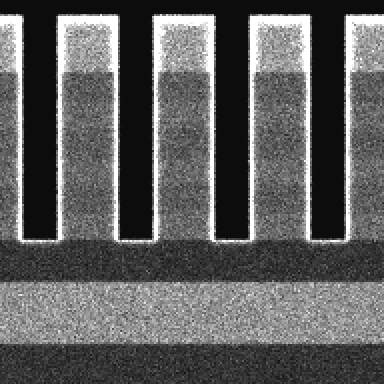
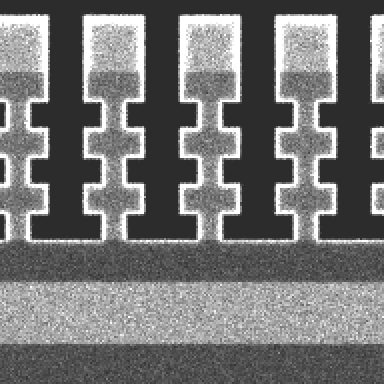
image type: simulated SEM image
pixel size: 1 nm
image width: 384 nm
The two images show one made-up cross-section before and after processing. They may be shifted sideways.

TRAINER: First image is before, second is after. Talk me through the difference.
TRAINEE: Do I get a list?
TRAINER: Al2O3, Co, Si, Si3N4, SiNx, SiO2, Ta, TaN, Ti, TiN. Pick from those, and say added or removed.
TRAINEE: removed: Si3N4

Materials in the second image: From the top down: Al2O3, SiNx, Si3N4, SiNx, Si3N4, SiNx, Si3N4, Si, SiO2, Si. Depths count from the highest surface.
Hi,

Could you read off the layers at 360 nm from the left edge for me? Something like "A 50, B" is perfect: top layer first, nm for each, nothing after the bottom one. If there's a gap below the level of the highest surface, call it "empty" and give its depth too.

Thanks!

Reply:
empty 224, Si 42, SiO2 62, Si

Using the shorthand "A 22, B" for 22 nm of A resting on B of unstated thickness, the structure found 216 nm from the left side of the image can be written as Al2O3 56, SiNx 30, Si3N4 26, SiNx 30, Si3N4 26, SiNx 30, Si3N4 26, Si 42, SiO2 62, Si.